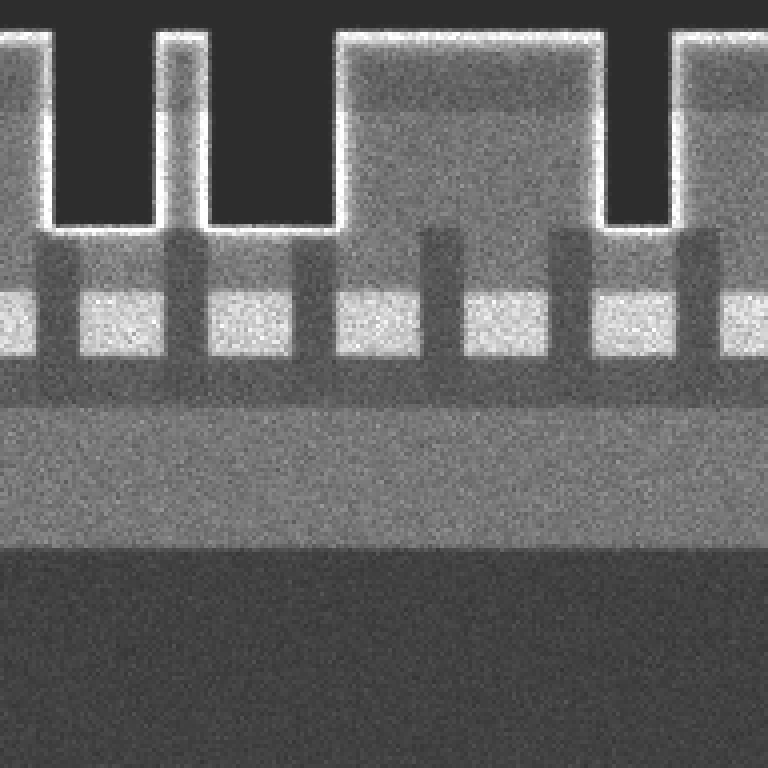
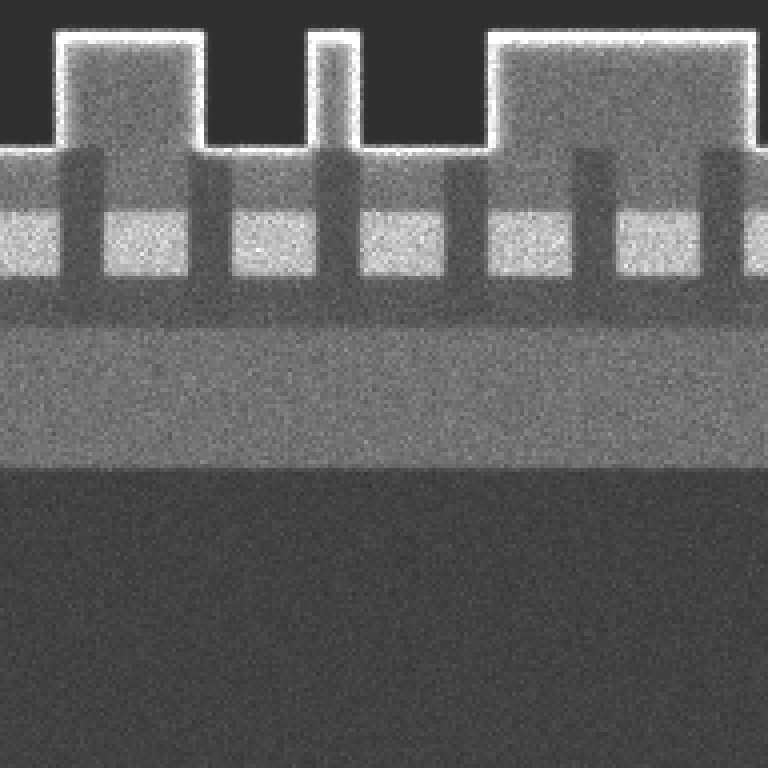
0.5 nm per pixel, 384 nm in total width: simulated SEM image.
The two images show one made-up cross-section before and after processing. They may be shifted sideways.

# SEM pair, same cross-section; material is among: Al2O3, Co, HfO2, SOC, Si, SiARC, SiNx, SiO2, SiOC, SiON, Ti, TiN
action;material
removed;SOC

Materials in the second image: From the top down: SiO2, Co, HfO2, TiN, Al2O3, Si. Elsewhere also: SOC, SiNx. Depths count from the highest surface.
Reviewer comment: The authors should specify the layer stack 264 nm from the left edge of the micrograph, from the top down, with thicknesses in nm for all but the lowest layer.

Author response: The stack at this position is SiO2 58, Co 32, HfO2 32, TiN 26, Al2O3 70, Si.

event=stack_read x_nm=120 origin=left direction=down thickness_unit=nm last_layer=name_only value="empty 58, Co 32, HfO2 32, TiN 26, Al2O3 70, Si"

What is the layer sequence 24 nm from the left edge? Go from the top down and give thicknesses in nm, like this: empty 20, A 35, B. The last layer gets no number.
empty 58, Co 32, HfO2 32, TiN 26, Al2O3 70, Si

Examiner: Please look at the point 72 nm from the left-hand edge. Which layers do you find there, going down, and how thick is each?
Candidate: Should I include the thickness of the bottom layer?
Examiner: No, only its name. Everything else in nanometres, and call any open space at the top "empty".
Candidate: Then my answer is SiO2 58, Co 32, HfO2 32, TiN 26, Al2O3 70, Si